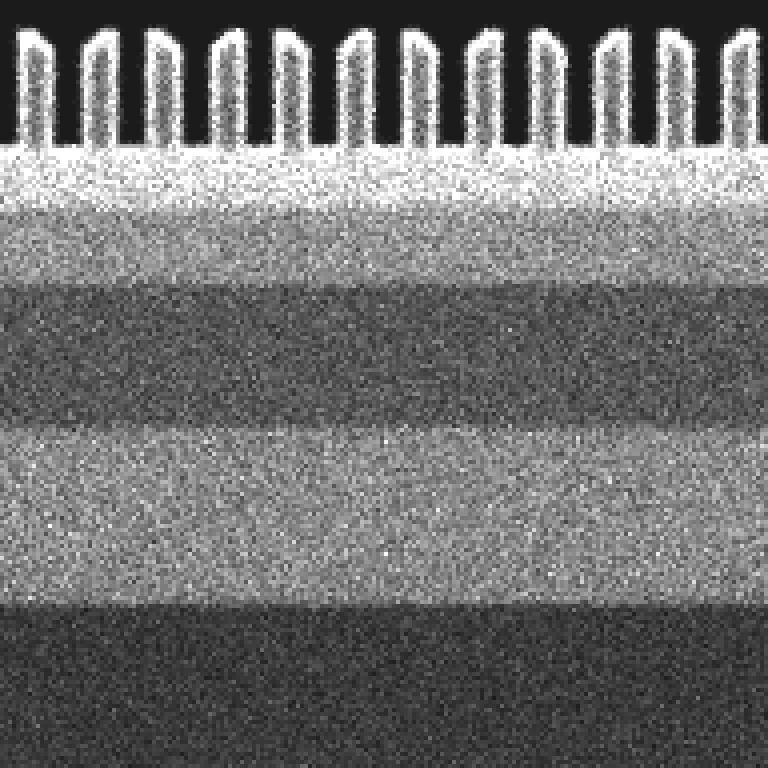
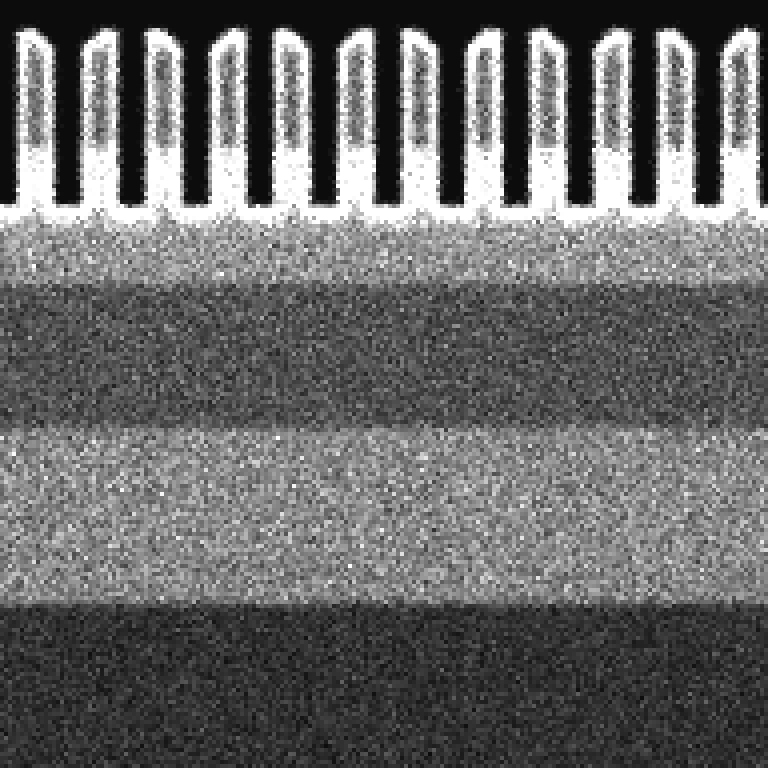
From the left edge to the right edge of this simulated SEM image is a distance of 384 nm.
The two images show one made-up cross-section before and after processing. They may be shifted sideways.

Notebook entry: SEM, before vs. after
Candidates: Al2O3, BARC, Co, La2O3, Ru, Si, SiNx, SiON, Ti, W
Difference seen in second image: W removed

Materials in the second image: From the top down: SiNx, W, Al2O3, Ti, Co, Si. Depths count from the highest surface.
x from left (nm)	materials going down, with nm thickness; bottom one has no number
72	empty 88, Al2O3 38, Ti 72, Co 88, Si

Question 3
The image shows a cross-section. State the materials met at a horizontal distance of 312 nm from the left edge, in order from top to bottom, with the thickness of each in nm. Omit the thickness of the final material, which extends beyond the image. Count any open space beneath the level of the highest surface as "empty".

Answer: SiNx 58, W 30, Al2O3 38, Ti 72, Co 88, Si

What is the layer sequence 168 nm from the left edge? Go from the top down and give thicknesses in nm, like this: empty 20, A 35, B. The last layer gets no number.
empty 88, Al2O3 38, Ti 72, Co 88, Si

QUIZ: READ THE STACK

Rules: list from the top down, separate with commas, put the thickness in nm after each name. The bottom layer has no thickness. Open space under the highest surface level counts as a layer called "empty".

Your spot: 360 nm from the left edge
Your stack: empty 88, Al2O3 38, Ti 72, Co 88, Si